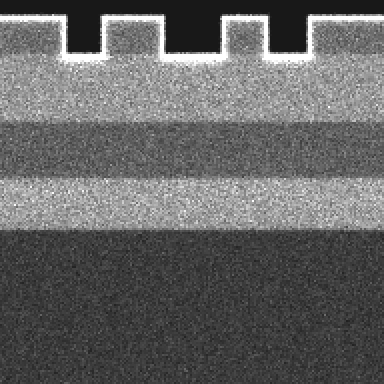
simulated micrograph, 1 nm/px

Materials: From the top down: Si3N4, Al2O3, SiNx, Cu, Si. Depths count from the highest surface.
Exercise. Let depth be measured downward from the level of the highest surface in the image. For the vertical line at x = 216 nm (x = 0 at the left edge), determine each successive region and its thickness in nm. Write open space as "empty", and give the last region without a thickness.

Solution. empty 38, Al2O3 68, SiNx 56, Cu 52, Si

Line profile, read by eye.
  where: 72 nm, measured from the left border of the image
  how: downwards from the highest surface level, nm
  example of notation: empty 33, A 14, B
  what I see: empty 38, Al2O3 68, SiNx 56, Cu 52, Si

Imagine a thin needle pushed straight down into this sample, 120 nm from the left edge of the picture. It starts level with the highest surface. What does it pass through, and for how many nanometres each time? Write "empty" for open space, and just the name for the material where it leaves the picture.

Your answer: Si3N4 38, Al2O3 68, SiNx 56, Cu 52, Si